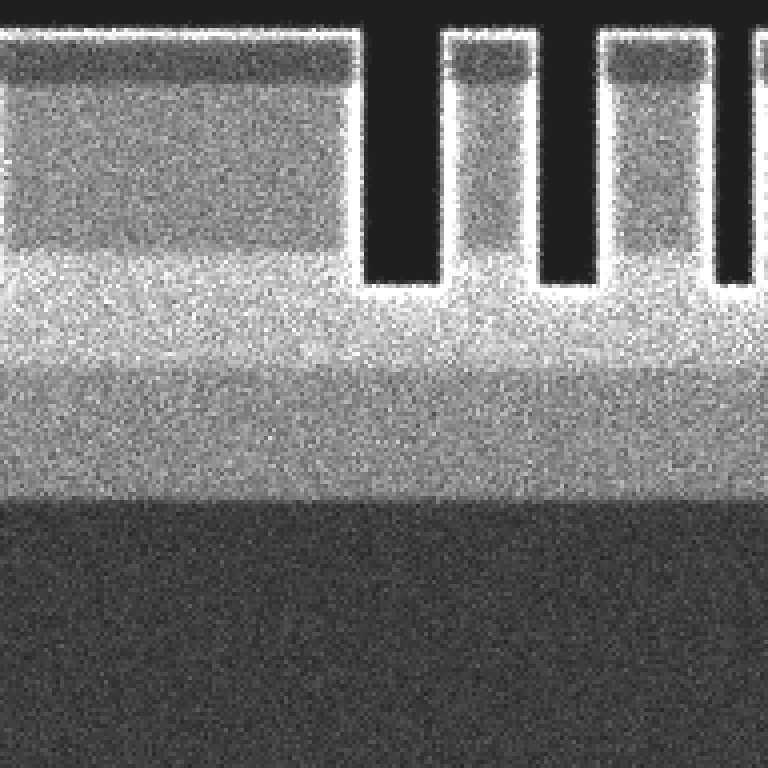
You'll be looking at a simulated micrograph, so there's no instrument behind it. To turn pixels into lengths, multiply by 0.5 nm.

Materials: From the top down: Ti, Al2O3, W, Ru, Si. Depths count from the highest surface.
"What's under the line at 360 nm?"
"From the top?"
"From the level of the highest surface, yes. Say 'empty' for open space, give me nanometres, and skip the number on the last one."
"empty 128, W 40, Ru 66, Si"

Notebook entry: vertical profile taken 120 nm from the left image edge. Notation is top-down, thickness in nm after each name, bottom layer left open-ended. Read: Ti 26, Al2O3 84, W 58, Ru 66, Si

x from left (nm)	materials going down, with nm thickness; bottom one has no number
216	empty 128, W 40, Ru 66, Si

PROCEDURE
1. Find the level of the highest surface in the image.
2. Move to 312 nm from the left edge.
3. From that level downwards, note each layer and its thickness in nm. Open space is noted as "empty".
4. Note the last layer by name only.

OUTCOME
Ti 26, Al2O3 84, W 58, Ru 66, Si